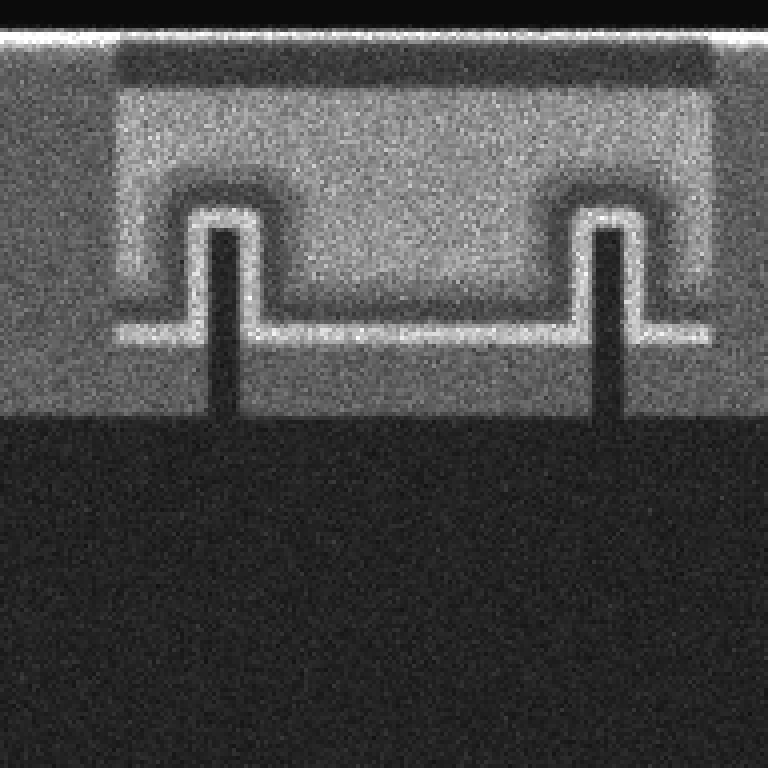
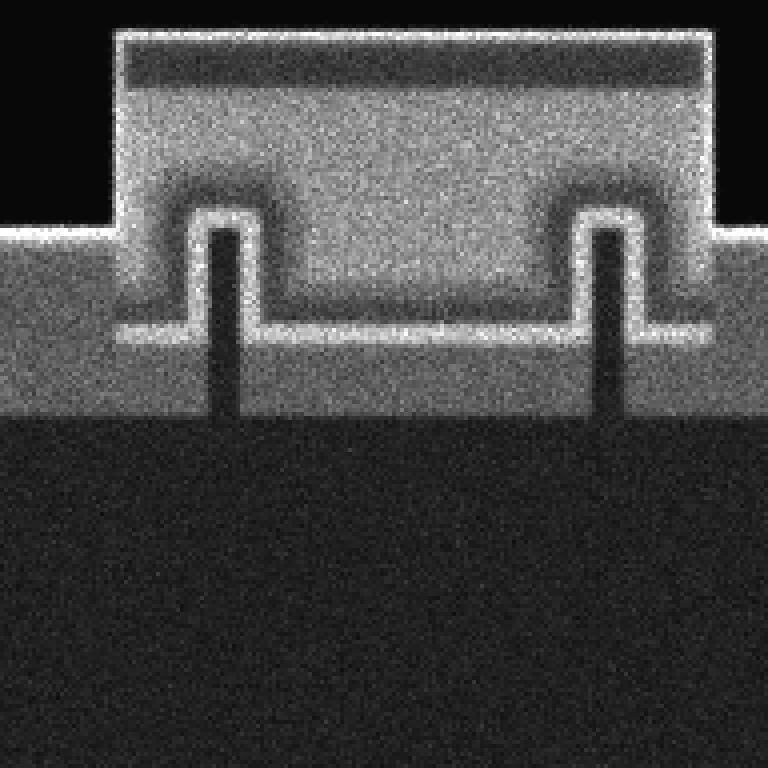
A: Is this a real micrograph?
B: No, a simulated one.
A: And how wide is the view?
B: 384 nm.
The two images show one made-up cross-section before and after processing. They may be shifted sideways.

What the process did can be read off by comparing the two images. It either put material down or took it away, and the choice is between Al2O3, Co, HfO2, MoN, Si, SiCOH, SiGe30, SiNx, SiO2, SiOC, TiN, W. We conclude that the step removed SiO2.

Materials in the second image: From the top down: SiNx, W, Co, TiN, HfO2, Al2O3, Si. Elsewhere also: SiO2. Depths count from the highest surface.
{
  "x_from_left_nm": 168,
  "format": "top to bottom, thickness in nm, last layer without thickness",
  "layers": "SiNx 28, W 96, Co 10, TiN 12, HfO2 10, Al2O3 36, Si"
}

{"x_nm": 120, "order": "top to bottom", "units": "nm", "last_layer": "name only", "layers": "SiNx 28, W 38, Co 10, TiN 12, HfO2 68, Al2O3 36, Si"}